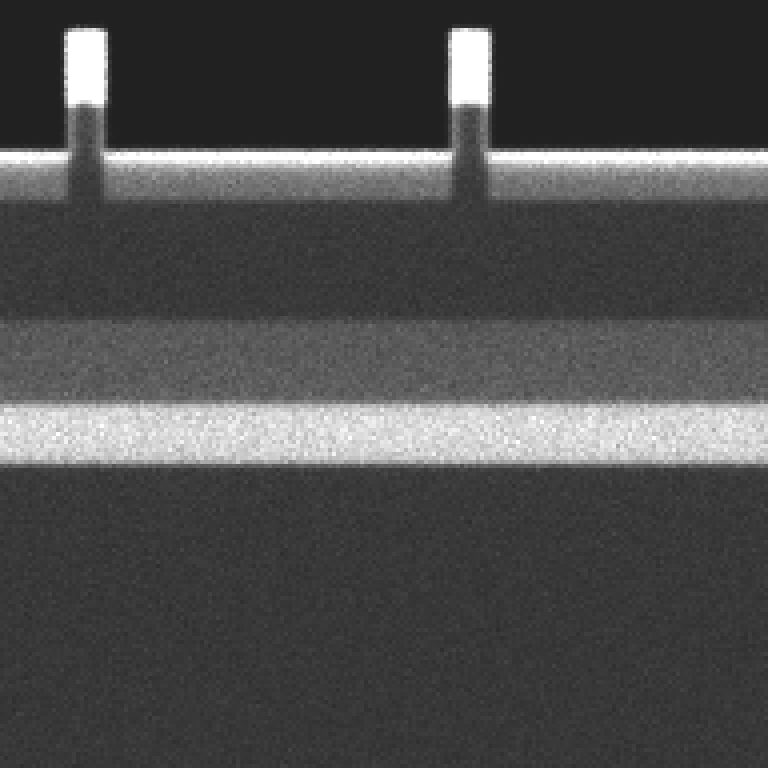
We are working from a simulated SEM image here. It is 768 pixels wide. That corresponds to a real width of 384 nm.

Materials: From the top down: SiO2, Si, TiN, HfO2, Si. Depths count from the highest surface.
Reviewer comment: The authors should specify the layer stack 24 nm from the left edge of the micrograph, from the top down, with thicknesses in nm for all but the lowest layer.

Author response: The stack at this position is empty 60, SiO2 24, Si 60, TiN 42, HfO2 30, Si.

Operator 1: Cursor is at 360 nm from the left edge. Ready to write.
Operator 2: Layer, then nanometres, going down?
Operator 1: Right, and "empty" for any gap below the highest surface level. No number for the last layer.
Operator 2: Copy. empty 60, SiO2 24, Si 60, TiN 42, HfO2 30, Si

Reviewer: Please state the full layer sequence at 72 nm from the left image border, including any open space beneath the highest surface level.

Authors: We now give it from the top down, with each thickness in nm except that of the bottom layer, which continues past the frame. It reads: empty 60, SiO2 24, Si 60, TiN 42, HfO2 30, Si